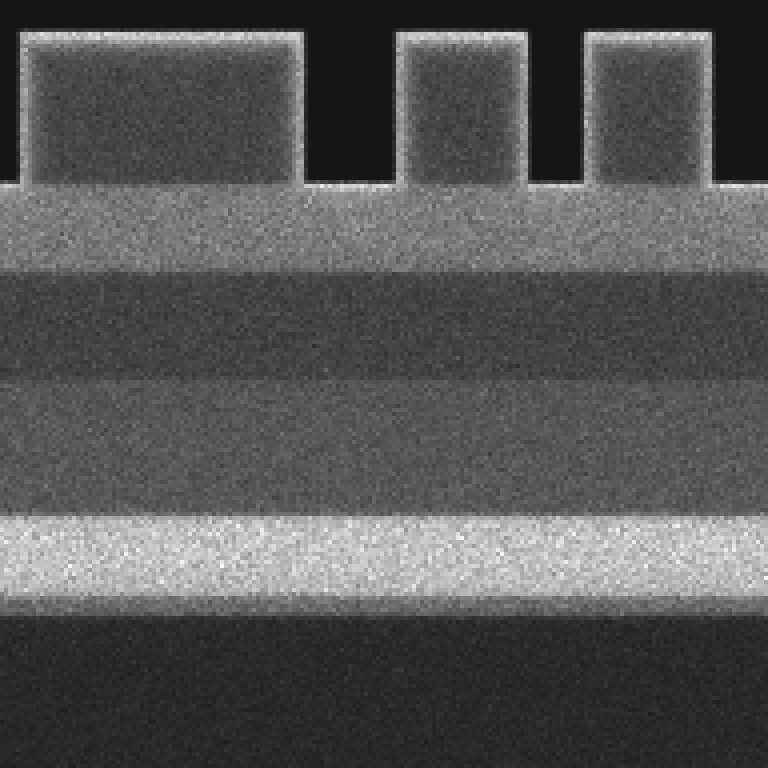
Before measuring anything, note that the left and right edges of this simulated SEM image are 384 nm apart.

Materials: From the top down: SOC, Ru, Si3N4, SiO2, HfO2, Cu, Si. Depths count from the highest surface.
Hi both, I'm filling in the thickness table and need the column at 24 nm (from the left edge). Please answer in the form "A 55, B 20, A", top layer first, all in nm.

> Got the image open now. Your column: SOC 76, Ru 44, Si3N4 54, SiO2 68, HfO2 40, Cu 10, Si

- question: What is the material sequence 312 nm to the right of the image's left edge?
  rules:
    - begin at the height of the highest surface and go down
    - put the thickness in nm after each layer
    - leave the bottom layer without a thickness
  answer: SOC 76, Ru 44, Si3N4 54, SiO2 68, HfO2 40, Cu 10, Si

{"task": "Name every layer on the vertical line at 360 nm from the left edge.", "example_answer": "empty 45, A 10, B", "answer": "empty 76, Ru 44, Si3N4 54, SiO2 68, HfO2 40, Cu 10, Si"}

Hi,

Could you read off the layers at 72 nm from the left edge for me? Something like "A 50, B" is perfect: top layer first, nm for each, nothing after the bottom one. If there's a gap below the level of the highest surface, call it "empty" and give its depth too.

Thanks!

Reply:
SOC 76, Ru 44, Si3N4 54, SiO2 68, HfO2 40, Cu 10, Si